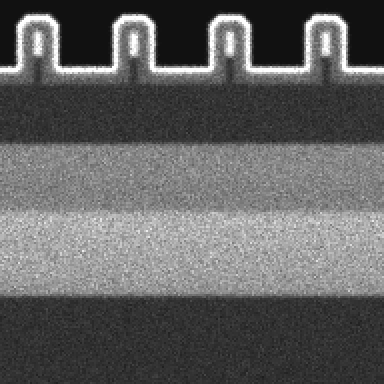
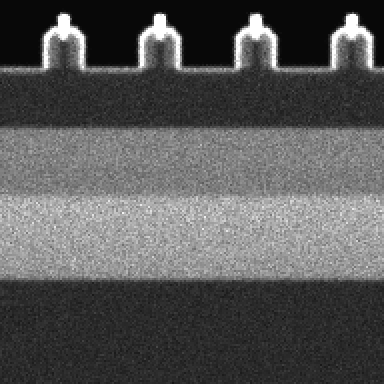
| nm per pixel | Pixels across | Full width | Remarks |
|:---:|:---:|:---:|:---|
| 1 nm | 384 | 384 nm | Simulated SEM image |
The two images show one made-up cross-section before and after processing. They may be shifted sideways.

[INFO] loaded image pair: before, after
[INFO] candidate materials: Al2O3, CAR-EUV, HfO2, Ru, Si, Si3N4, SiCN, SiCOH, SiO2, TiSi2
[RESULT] removed Si3N4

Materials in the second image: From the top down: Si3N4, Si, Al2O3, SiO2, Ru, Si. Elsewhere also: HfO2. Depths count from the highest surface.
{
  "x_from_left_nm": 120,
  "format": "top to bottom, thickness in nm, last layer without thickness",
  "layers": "empty 52, Si 60, Al2O3 38, SiO2 30, Ru 84, Si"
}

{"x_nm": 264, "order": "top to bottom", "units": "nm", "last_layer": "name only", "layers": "empty 12, Si3N4 40, Si 60, Al2O3 38, SiO2 30, Ru 84, Si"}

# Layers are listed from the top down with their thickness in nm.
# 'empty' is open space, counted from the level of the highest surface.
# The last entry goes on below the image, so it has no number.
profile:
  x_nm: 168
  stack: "empty 12, Si3N4 40, Si 60, Al2O3 38, SiO2 30, Ru 84, Si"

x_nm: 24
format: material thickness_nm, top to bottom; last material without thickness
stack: empty 52, Si 60, Al2O3 38, SiO2 30, Ru 84, Si